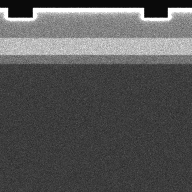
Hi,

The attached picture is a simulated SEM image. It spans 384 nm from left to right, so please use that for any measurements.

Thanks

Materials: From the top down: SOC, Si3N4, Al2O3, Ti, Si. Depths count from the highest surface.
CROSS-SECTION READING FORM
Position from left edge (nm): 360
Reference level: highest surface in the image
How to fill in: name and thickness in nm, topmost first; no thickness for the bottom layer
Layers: SOC 20, Si3N4 40, Al2O3 34, Ti 18, Si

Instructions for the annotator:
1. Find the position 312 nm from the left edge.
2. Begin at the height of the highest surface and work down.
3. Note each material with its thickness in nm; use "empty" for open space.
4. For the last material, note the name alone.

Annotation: empty 20, Si3N4 40, Al2O3 34, Ti 18, Si